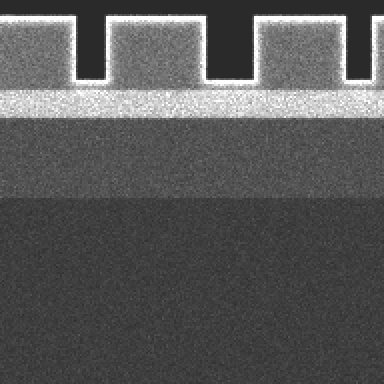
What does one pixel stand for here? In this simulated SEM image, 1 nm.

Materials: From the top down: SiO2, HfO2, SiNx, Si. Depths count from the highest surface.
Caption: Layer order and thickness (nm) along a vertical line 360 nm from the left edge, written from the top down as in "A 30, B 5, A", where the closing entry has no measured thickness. empty 64, SiO2 10, HfO2 28, SiNx 80, Si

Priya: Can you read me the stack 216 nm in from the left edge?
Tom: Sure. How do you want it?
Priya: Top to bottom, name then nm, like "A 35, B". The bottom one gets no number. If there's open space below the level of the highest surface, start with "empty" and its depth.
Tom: empty 64, SiO2 10, HfO2 28, SiNx 80, Si